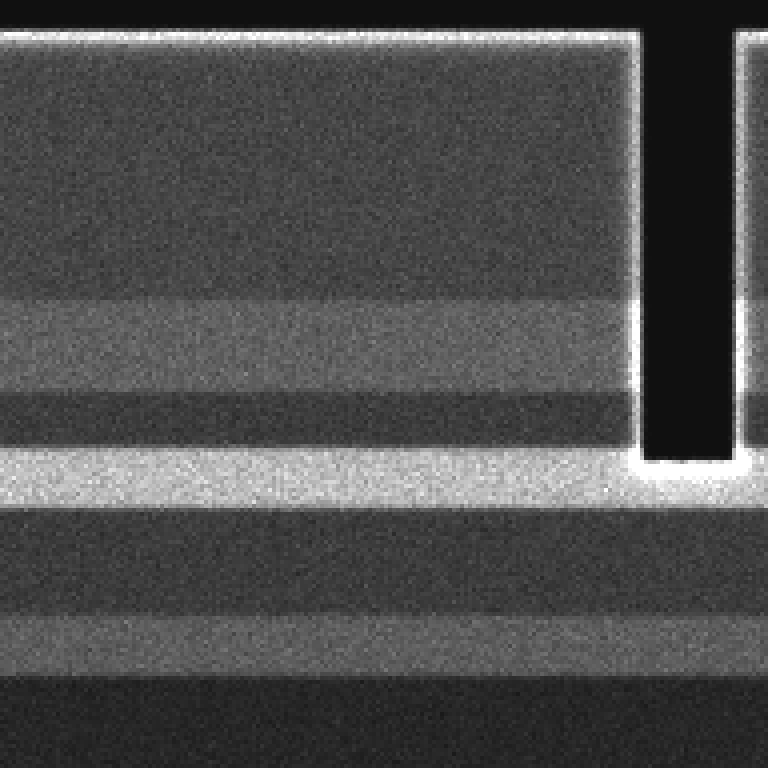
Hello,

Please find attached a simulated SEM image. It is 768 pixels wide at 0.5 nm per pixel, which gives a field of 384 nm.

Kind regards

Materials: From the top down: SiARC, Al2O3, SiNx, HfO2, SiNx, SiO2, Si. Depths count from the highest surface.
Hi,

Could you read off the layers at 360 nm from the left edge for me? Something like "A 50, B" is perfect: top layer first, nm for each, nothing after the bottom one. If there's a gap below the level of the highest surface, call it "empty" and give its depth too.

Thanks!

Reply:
empty 216, HfO2 22, SiNx 54, SiO2 30, Si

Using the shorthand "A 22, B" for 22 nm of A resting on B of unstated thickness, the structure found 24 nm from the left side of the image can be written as SiARC 134, Al2O3 46, SiNx 28, HfO2 30, SiNx 54, SiO2 30, Si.